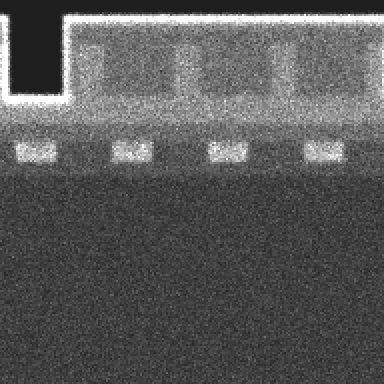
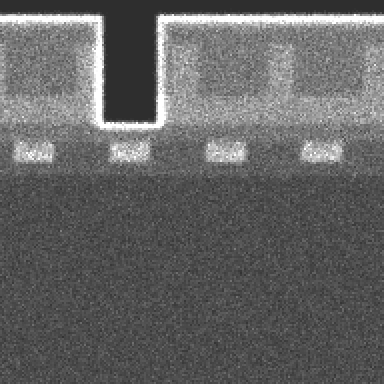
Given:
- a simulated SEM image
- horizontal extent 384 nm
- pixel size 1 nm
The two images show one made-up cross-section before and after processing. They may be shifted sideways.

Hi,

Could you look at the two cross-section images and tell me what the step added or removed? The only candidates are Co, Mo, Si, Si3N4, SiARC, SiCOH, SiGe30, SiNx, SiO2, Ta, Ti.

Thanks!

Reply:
removed SiO2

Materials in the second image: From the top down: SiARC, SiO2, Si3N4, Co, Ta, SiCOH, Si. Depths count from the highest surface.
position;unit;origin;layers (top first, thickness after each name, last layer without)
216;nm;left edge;SiARC 80, SiO2 28, Si3N4 18, Co 10, Ta 10, SiCOH 14, Si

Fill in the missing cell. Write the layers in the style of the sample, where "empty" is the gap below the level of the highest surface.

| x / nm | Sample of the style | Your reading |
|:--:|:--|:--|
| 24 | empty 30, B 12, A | SiARC 80, SiO2 28, Si3N4 18, Co 10, Ta 10, SiCOH 14, Si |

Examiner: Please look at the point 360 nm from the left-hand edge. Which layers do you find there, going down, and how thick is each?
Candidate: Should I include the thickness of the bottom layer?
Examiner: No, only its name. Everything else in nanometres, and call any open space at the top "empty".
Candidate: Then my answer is SiARC 80, SiO2 28, Si3N4 18, SiCOH 34, Si